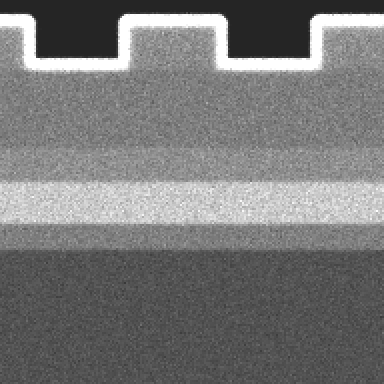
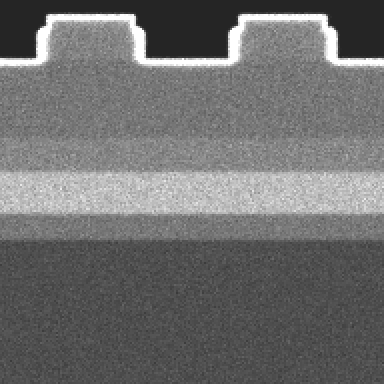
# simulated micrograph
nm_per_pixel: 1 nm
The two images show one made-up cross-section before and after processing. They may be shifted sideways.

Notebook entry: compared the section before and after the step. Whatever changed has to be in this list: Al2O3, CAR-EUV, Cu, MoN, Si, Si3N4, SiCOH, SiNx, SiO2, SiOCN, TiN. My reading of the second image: SiO2 removed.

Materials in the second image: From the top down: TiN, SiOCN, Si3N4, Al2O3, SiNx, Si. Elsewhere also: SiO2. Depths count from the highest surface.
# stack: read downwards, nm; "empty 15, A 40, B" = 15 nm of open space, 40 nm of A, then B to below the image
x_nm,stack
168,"empty 44, SiOCN 78, Si3N4 34, Al2O3 42, SiNx 26, Si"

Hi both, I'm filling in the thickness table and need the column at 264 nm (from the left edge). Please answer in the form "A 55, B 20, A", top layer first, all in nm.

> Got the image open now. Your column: TiN 44, SiOCN 78, Si3N4 34, Al2O3 42, SiNx 26, Si